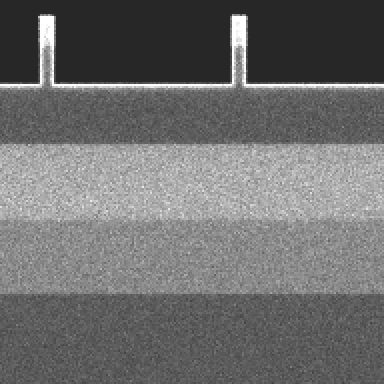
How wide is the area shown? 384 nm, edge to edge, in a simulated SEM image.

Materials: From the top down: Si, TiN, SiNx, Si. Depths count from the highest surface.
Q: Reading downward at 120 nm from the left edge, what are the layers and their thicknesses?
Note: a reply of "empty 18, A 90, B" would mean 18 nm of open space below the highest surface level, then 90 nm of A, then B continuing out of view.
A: empty 68, Si 60, TiN 76, SiNx 74, Si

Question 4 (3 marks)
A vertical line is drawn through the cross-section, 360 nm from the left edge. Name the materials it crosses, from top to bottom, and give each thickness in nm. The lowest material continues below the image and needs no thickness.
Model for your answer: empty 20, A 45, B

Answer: empty 68, Si 60, TiN 76, SiNx 74, Si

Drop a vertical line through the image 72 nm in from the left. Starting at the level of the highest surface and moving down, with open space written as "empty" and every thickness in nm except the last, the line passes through empty 68, Si 60, TiN 76, SiNx 74, Si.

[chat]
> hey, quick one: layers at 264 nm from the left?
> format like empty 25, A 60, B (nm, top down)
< empty 68, Si 60, TiN 76, SiNx 74, Si